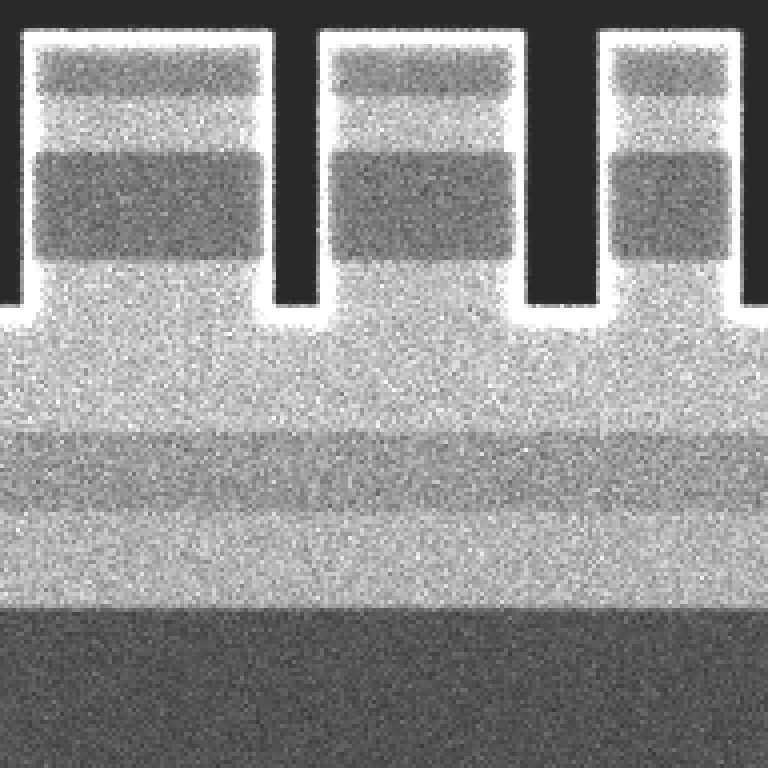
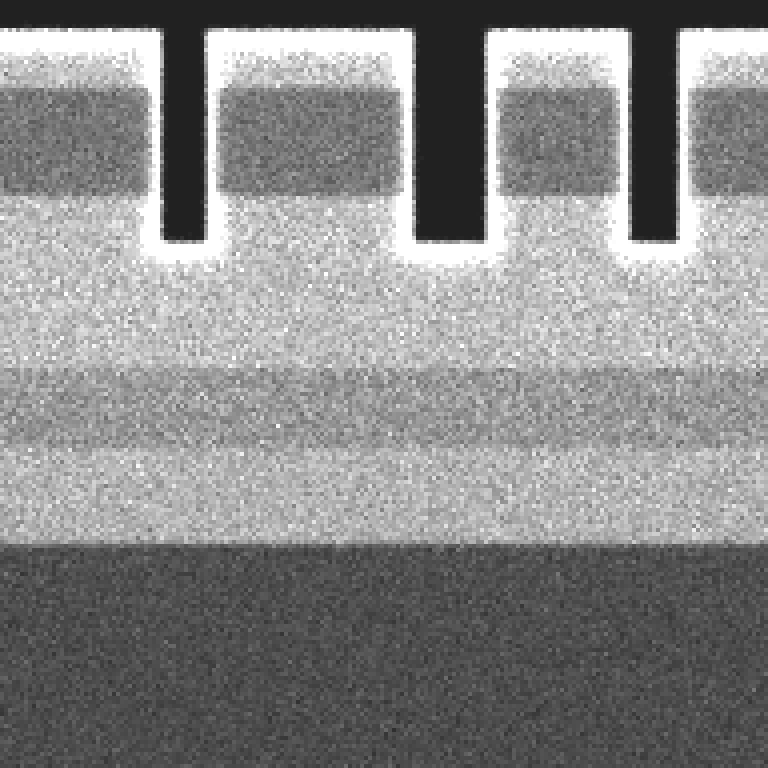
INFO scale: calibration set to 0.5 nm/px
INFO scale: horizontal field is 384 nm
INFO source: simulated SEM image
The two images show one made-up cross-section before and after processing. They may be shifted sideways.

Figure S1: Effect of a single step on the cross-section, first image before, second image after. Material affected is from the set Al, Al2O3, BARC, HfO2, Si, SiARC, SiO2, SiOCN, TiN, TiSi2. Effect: removed SiARC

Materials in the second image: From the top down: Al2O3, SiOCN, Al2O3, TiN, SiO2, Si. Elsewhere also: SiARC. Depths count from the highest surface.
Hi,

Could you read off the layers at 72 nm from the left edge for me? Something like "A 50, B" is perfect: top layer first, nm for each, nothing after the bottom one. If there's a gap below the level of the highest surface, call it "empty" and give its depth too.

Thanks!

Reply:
Al2O3 28, SiOCN 54, Al2O3 86, TiN 40, SiO2 48, Si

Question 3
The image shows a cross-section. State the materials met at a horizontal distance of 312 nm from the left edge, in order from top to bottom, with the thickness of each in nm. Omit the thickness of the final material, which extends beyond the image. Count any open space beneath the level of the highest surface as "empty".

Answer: Al2O3 28, SiOCN 54, Al2O3 86, TiN 40, SiO2 48, Si